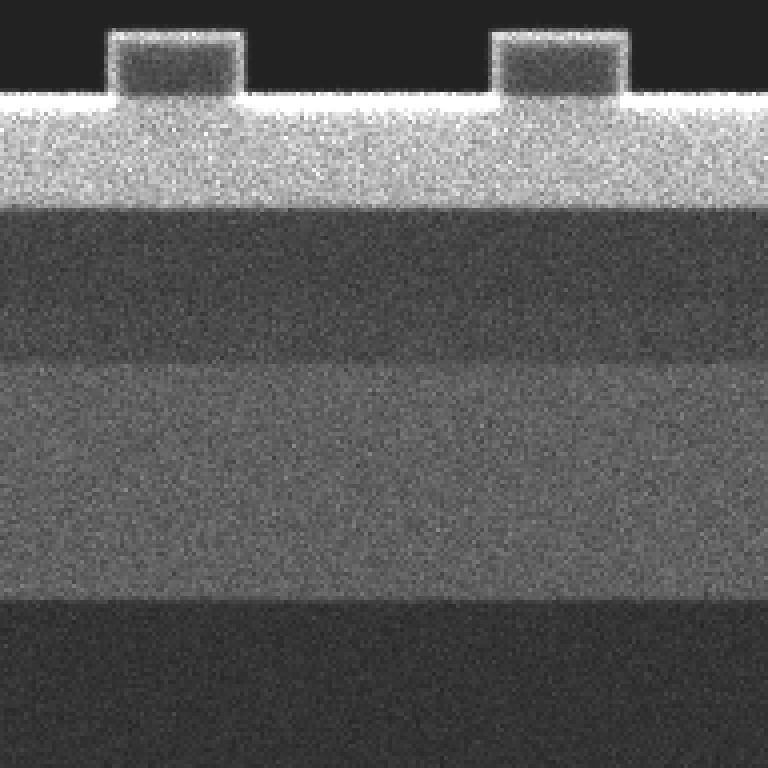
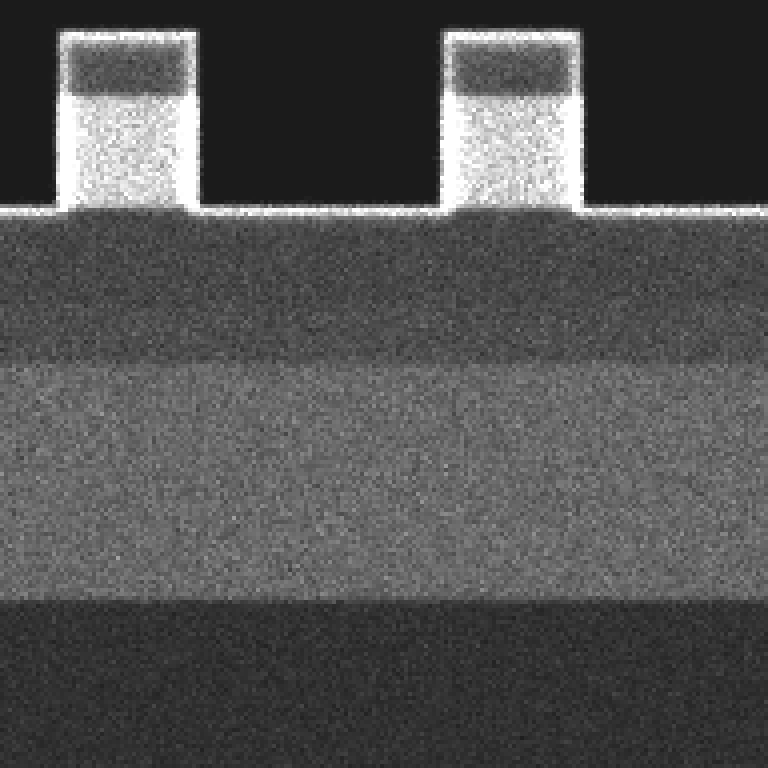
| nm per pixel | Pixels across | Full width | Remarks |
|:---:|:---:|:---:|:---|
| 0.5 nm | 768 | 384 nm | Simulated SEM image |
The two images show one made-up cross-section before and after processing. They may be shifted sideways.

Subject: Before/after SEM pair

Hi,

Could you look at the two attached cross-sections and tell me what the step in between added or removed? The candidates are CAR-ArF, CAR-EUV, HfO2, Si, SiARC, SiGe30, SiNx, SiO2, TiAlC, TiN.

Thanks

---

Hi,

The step removed HfO2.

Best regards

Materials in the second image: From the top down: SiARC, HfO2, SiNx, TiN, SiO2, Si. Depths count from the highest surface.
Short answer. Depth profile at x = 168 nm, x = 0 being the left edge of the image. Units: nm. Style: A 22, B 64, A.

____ empty 88, SiNx 48, TiN 30, SiO2 118, Si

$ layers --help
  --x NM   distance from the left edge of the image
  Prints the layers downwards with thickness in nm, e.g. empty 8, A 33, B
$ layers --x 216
empty 88, SiNx 48, TiN 30, SiO2 118, Si